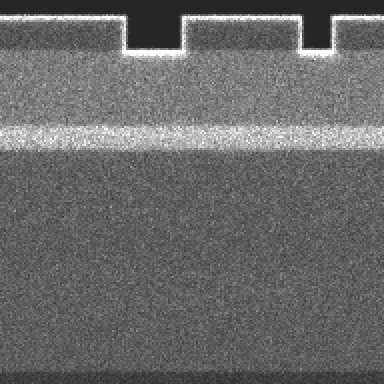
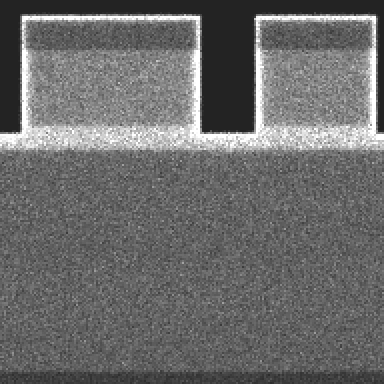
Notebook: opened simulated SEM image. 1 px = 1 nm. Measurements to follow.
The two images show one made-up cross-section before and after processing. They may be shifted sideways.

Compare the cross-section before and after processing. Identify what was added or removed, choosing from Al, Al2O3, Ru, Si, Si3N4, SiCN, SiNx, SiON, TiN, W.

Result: Al2O3 and W removed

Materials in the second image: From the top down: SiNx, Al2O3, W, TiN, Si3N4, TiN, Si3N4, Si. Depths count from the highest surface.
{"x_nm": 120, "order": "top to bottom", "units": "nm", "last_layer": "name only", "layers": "SiNx 34, Al2O3 76, W 24, TiN 80, Si3N4 36, TiN 52, Si3N4 54, Si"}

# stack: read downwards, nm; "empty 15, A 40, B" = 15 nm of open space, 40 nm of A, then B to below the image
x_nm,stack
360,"SiNx 34, Al2O3 76, W 24, TiN 80, Si3N4 36, TiN 52, Si3N4 54, Si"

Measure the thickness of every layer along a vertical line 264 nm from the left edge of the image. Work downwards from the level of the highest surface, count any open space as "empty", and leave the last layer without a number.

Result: SiNx 34, Al2O3 76, W 24, TiN 80, Si3N4 36, TiN 52, Si3N4 54, Si